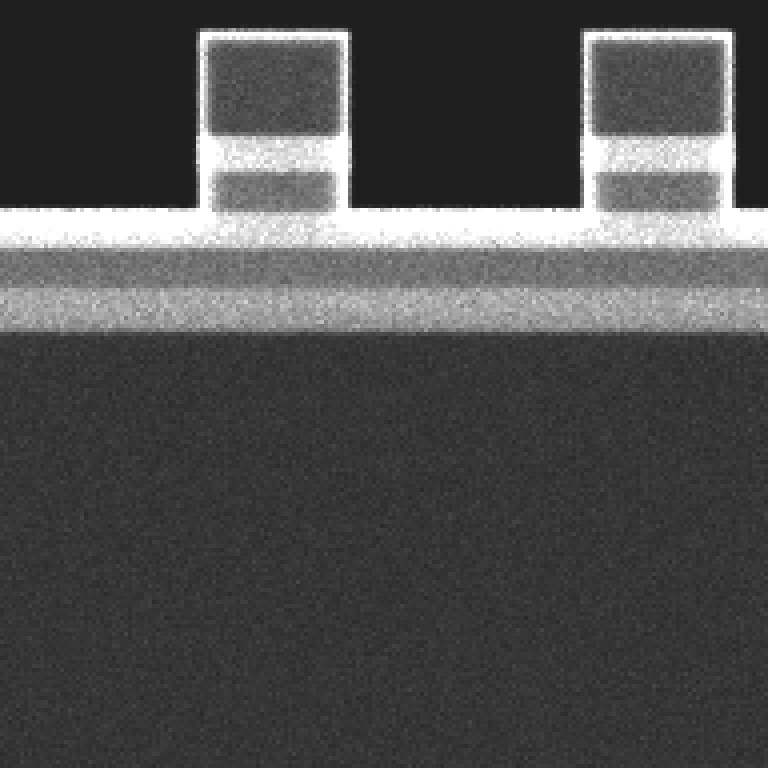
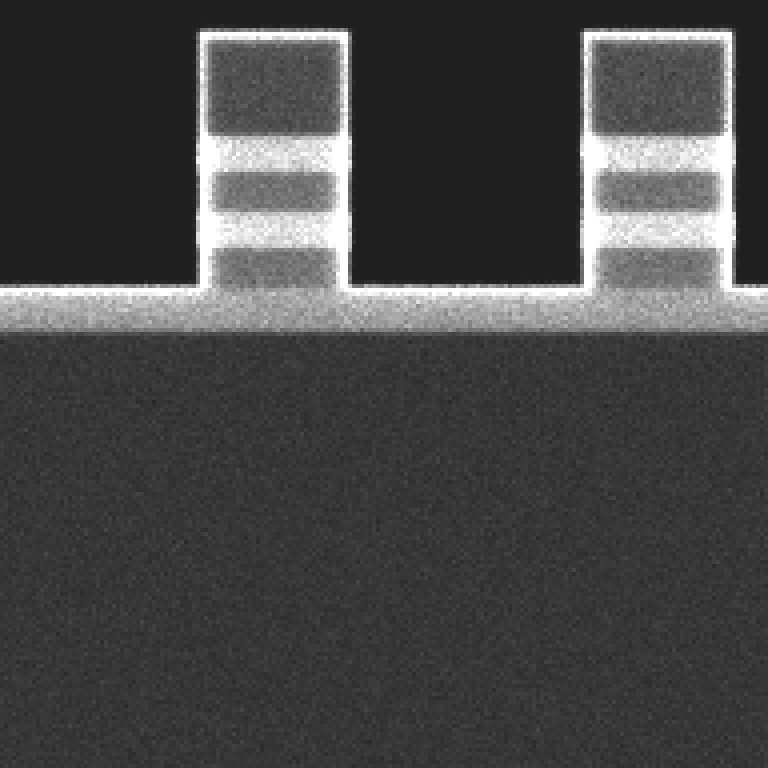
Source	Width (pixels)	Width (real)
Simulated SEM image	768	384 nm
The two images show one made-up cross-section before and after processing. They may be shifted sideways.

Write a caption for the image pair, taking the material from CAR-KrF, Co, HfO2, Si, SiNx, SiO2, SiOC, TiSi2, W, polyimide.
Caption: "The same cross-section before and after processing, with HfO2 and SiO2 removed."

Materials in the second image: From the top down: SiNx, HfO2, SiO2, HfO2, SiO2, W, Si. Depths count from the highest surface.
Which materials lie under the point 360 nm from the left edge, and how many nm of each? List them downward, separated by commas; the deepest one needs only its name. SiNx 52, HfO2 18, SiO2 20, HfO2 18, SiO2 20, W 22, Si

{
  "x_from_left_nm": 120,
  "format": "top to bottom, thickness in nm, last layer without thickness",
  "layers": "SiNx 52, HfO2 18, SiO2 20, HfO2 18, SiO2 20, W 22, Si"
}